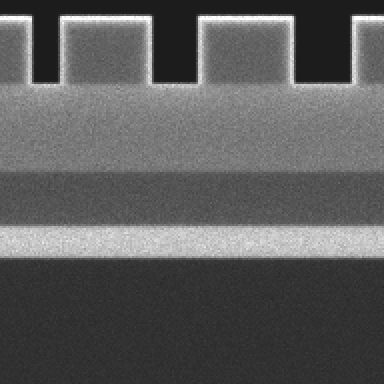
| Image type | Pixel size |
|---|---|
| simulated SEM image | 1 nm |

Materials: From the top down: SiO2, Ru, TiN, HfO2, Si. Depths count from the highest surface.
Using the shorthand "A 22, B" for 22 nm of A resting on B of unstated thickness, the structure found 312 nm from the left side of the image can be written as empty 68, Ru 88, TiN 54, HfO2 32, Si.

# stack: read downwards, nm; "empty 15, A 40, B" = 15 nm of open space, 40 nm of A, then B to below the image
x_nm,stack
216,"SiO2 68, Ru 88, TiN 54, HfO2 32, Si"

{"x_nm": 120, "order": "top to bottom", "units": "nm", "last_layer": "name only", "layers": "SiO2 68, Ru 88, TiN 54, HfO2 32, Si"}